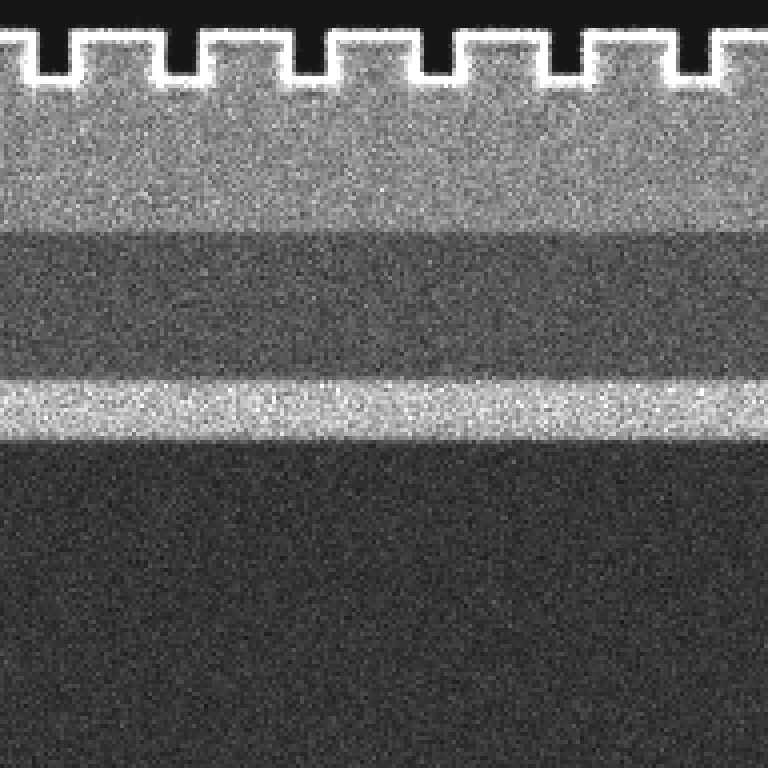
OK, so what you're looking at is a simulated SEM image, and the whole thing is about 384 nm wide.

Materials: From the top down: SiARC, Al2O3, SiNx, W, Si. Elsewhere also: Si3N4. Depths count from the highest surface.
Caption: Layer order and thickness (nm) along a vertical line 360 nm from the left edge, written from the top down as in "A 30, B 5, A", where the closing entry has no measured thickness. Si3N4 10, Al2O3 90, SiNx 74, W 30, Si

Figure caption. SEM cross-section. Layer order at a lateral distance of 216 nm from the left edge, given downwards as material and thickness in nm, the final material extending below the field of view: empty 22, SiARC 12, Al2O3 66, SiNx 74, W 30, Si